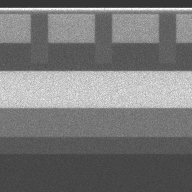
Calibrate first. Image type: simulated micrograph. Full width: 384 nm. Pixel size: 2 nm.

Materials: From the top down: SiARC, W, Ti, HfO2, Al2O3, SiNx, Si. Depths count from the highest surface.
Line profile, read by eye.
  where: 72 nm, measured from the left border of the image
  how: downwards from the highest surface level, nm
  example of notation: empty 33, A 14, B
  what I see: SiARC 110, Ti 16, HfO2 74, Al2O3 58, SiNx 34, Si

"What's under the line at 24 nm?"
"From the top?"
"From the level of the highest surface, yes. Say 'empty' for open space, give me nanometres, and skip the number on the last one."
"SiARC 12, W 58, Ti 56, HfO2 74, Al2O3 58, SiNx 34, Si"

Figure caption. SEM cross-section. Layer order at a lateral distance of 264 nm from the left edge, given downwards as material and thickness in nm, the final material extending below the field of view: SiARC 12, W 58, Ti 56, HfO2 74, Al2O3 58, SiNx 34, Si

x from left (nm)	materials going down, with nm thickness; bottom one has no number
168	SiARC 12, W 58, Ti 56, HfO2 74, Al2O3 58, SiNx 34, Si